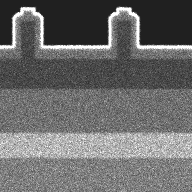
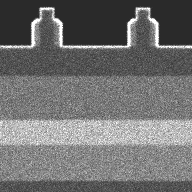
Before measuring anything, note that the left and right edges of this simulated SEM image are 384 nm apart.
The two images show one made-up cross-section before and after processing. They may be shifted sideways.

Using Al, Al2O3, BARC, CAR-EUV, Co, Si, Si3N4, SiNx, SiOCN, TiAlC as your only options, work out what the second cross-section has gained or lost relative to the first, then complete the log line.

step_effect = removed SiOCN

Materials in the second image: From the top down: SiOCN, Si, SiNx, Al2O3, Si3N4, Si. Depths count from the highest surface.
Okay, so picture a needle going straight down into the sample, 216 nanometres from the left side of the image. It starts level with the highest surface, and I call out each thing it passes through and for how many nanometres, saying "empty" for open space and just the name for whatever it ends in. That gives empty 76, Si 60, SiNx 88, Al2O3 50, Si3N4 72, Si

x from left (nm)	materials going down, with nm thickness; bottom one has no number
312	empty 28, SiOCN 48, Si 60, SiNx 88, Al2O3 50, Si3N4 72, Si